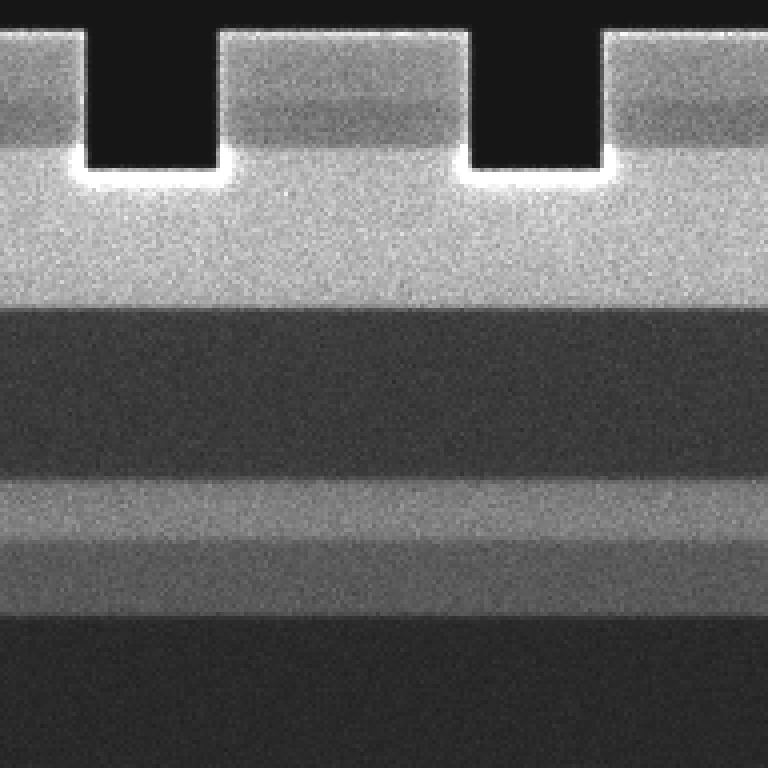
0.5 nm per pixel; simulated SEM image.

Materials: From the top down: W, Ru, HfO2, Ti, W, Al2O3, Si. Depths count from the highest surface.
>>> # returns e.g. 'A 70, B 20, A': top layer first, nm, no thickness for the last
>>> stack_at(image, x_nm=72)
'empty 70, HfO2 68, Ti 86, W 30, Al2O3 38, Si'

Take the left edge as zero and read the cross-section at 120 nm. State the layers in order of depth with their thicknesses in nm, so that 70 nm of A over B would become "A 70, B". W 34, Ru 24, HfO2 80, Ti 86, W 30, Al2O3 38, Si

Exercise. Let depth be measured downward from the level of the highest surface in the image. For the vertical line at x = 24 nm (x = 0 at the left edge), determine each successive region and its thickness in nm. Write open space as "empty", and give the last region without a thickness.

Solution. W 34, Ru 24, HfO2 80, Ti 86, W 30, Al2O3 38, Si